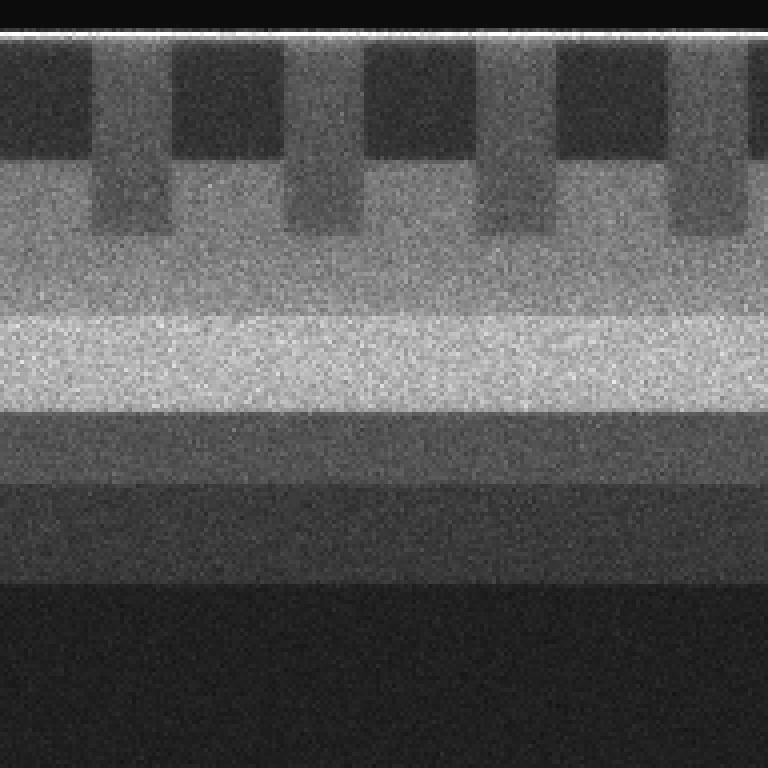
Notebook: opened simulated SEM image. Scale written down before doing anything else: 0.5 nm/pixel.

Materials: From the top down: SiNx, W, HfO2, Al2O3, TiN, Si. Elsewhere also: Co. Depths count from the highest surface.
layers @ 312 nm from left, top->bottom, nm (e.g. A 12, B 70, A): SiNx 64, W 78, HfO2 48, Al2O3 36, TiN 50, Si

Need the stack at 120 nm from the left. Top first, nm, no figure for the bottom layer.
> SiNx 64, W 78, HfO2 48, Al2O3 36, TiN 50, Si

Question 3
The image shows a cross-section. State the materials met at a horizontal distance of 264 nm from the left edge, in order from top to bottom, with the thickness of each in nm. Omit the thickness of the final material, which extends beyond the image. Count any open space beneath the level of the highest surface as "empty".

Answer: Co 102, W 40, HfO2 48, Al2O3 36, TiN 50, Si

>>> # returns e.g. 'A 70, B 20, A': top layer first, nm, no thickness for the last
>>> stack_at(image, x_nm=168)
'Co 102, W 40, HfO2 48, Al2O3 36, TiN 50, Si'